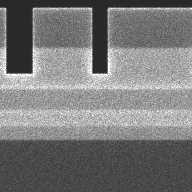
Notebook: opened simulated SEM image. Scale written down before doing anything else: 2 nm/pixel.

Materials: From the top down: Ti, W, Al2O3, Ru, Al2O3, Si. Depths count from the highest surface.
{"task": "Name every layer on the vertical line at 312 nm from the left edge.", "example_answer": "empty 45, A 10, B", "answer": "Ti 80, W 82, Al2O3 42, Ru 32, Al2O3 28, Si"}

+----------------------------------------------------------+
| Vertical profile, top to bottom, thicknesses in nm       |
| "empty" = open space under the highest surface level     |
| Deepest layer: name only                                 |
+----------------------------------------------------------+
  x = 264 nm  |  Ti 80, W 82, Al2O3 42, Ru 32, Al2O3 28, Si